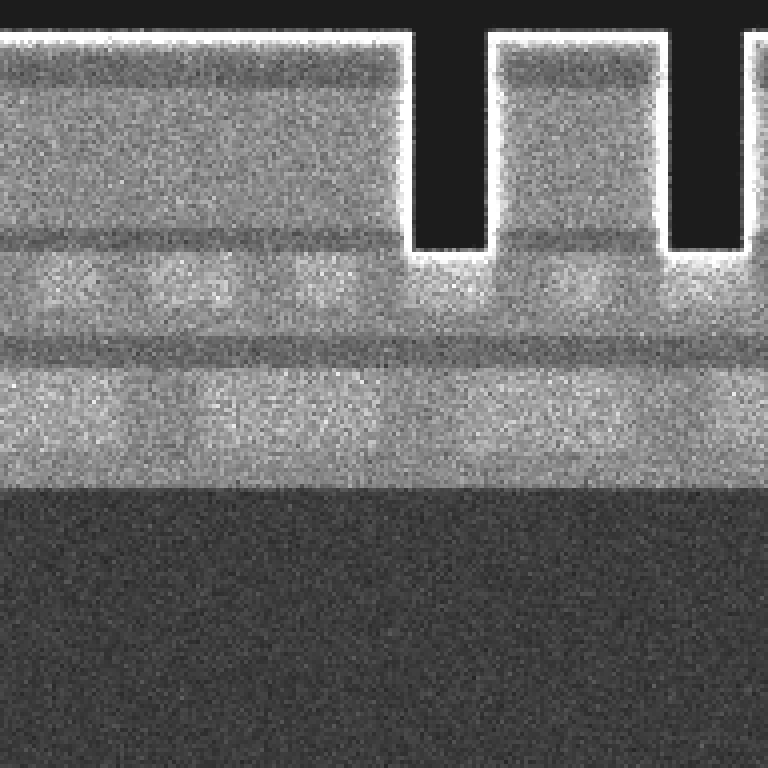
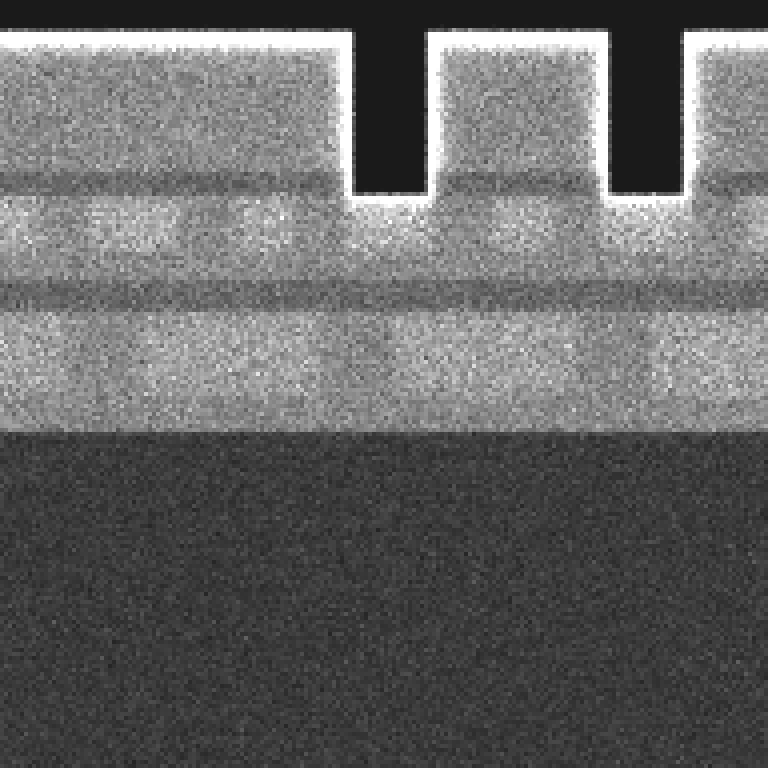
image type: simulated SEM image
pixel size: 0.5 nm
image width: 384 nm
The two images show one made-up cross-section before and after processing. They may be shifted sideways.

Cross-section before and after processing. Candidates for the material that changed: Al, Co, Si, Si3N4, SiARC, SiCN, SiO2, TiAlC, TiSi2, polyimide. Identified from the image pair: SiARC (removed).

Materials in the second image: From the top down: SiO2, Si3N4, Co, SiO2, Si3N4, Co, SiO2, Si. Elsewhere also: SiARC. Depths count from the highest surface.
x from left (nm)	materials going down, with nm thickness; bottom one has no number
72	SiO2 70, Si3N4 12, Co 28, SiO2 14, Si3N4 16, Co 42, SiO2 18, Si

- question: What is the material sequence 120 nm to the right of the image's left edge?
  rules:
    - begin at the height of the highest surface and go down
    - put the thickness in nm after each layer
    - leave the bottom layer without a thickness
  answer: SiO2 70, Si3N4 12, Co 28, SiO2 14, Si3N4 16, Co 42, SiO2 18, Si